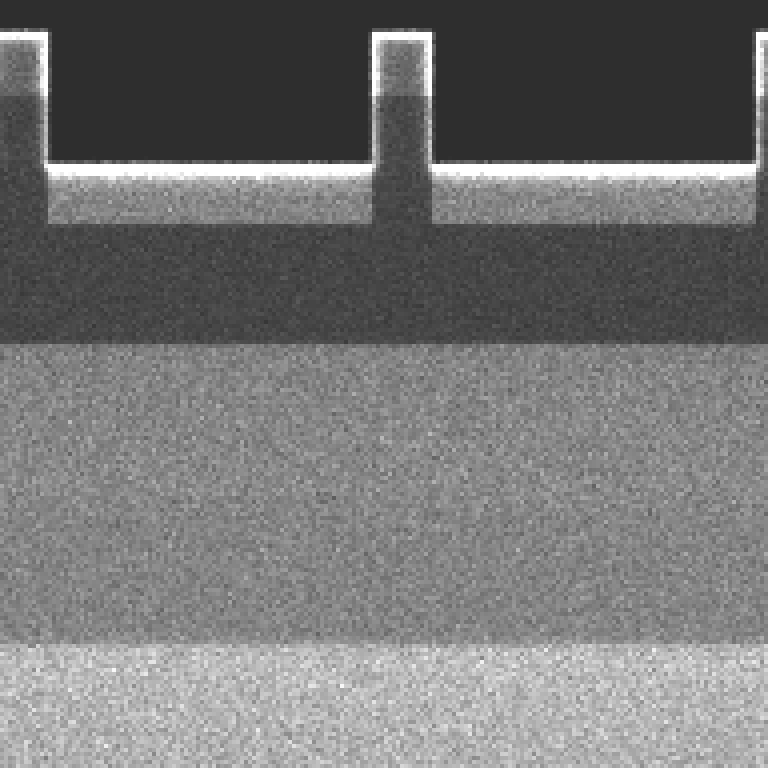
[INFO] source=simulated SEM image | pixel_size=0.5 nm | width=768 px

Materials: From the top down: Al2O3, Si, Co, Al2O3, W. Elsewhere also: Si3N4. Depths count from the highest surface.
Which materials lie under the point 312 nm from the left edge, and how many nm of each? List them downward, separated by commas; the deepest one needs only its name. empty 66, Al2O3 30, Si 60, Co 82, Al2O3 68, W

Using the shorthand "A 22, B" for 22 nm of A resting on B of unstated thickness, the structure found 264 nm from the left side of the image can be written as empty 66, Al2O3 30, Si 60, Co 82, Al2O3 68, W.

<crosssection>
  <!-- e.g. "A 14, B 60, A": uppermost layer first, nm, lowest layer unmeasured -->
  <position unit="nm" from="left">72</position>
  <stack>empty 66, Al2O3 30, Si 60, Co 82, Al2O3 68, W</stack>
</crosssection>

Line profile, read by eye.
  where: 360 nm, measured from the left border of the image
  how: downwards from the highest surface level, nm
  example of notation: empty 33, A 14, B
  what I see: empty 66, Al2O3 30, Si 60, Co 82, Al2O3 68, W